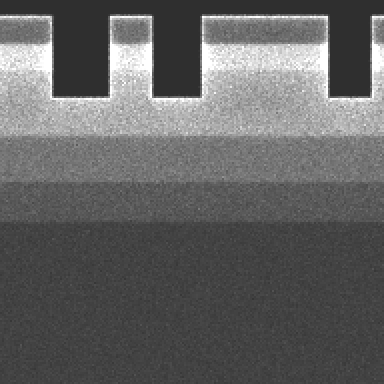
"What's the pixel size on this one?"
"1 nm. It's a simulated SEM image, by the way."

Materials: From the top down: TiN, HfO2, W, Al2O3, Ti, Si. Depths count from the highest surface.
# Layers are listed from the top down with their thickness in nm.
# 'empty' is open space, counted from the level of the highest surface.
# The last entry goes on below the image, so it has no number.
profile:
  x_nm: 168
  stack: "empty 82, W 38, Al2O3 46, Ti 40, Si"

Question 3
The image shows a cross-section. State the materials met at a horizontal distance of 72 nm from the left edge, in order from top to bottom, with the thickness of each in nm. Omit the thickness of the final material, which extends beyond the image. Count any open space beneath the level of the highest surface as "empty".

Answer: empty 82, W 38, Al2O3 46, Ti 40, Si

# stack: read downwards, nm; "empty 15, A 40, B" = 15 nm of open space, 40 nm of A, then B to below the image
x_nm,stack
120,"TiN 28, HfO2 26, W 66, Al2O3 46, Ti 40, Si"